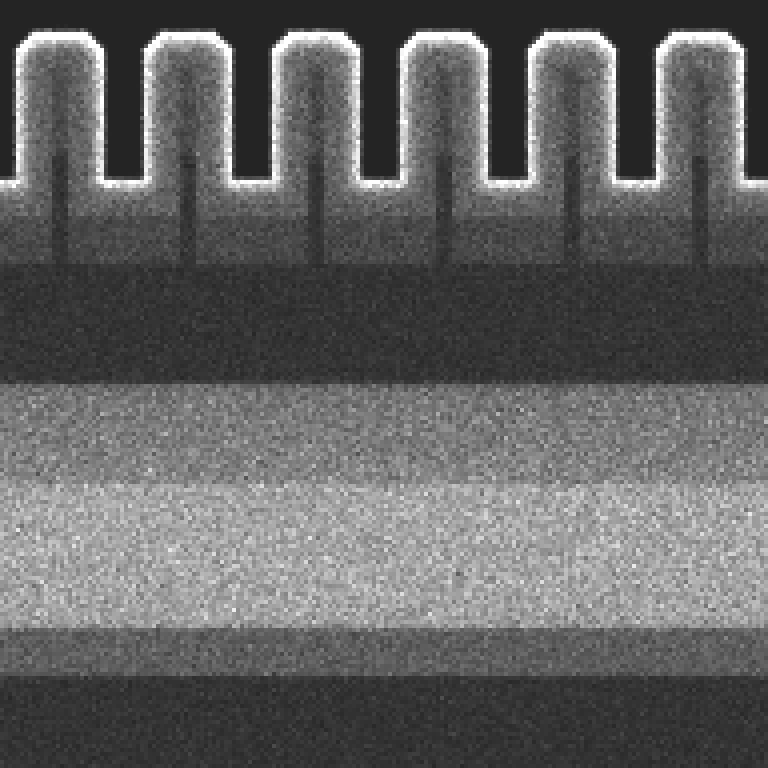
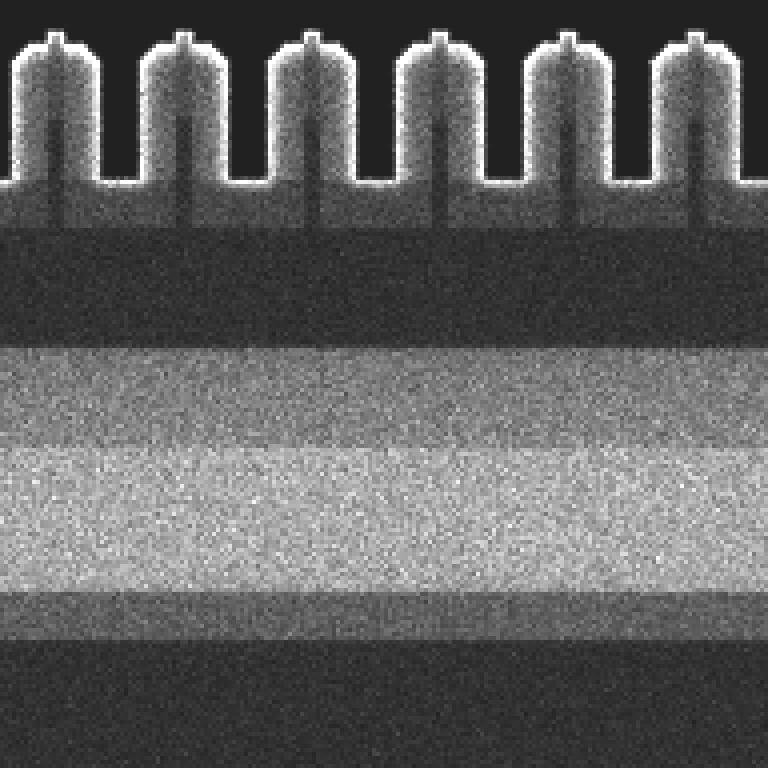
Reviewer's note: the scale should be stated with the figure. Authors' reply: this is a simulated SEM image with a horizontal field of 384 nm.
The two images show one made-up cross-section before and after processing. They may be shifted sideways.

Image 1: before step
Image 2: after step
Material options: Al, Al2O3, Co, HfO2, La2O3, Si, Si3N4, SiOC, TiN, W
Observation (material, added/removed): Al2O3, removed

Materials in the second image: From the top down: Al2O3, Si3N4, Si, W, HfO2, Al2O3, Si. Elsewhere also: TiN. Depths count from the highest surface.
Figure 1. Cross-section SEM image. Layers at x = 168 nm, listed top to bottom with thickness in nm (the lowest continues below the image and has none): empty 6, Al2O3 68, Si3N4 24, Si 60, W 50, HfO2 72, Al2O3 24, Si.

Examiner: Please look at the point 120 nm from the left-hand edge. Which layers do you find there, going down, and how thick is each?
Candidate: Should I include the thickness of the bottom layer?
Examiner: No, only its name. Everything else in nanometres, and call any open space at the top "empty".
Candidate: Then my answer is empty 74, Si3N4 24, Si 60, W 50, HfO2 72, Al2O3 24, Si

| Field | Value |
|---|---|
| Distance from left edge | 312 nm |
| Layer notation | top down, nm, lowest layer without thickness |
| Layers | empty 74, Si3N4 24, Si 60, W 50, HfO2 72, Al2O3 24, Si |